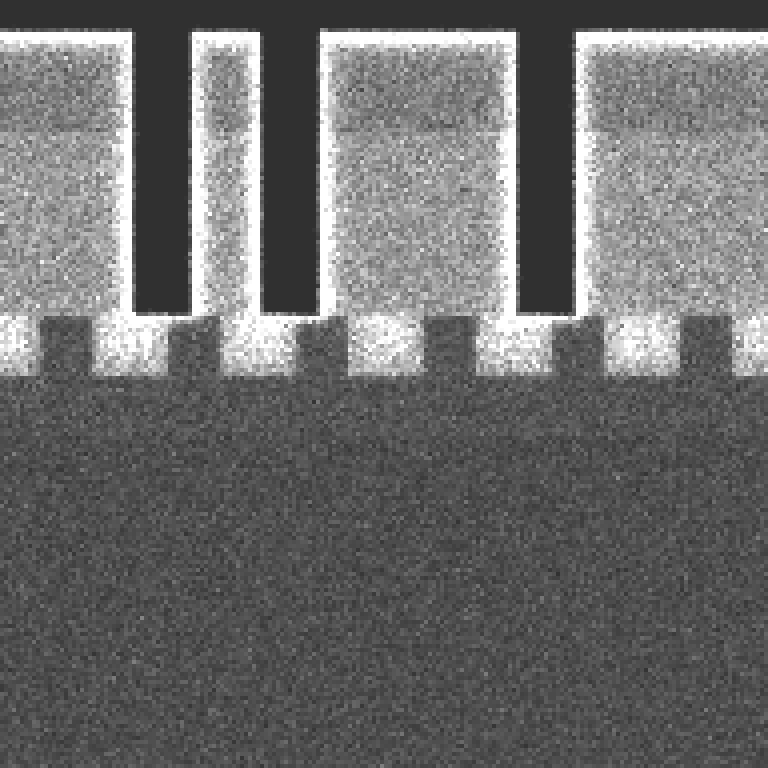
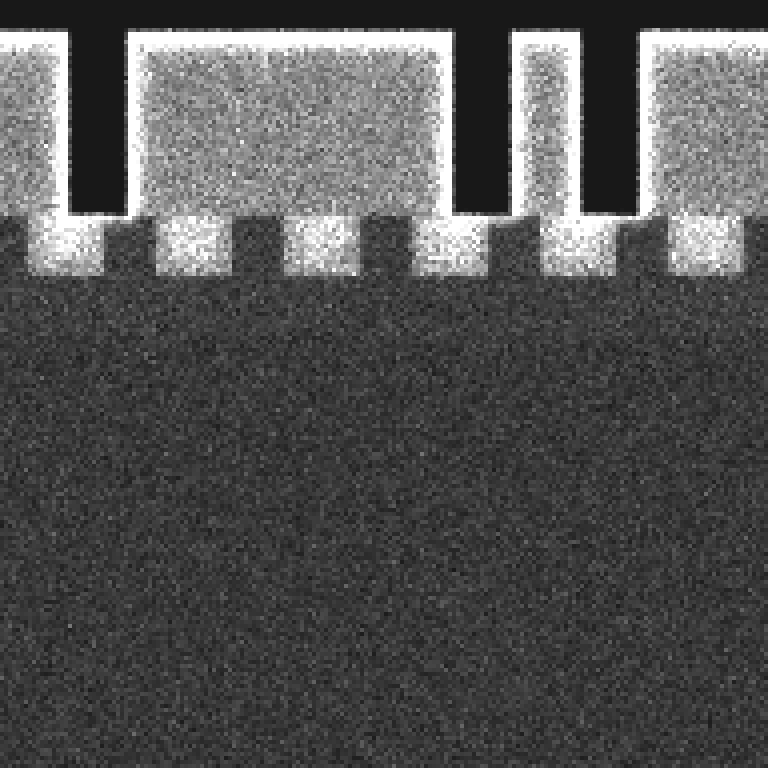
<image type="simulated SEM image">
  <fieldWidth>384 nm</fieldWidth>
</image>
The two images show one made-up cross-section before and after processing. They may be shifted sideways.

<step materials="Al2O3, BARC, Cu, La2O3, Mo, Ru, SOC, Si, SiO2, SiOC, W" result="removed SOC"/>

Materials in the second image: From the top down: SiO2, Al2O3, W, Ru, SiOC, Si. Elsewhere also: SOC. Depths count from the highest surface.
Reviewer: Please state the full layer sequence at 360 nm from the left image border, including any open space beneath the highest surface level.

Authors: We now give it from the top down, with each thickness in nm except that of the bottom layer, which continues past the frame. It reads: SiO2 80, Al2O3 12, W 22, Ru 8, SiOC 30, Si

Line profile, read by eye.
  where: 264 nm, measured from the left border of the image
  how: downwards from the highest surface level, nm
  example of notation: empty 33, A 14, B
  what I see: SiO2 80, Al2O3 12, SiOC 60, Si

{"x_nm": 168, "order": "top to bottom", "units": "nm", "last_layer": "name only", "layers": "SiO2 80, Al2O3 12, W 22, Ru 8, SiOC 30, Si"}